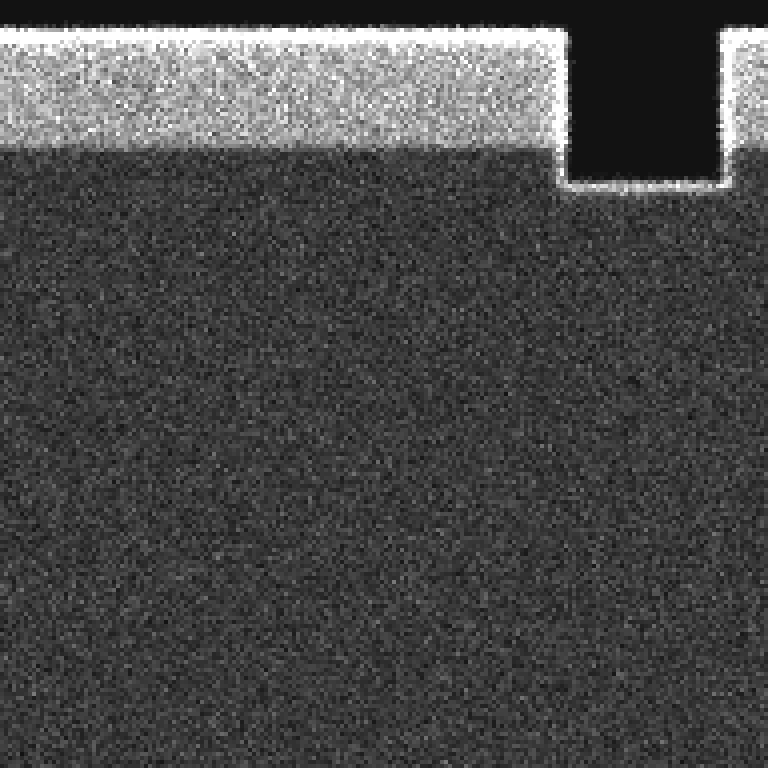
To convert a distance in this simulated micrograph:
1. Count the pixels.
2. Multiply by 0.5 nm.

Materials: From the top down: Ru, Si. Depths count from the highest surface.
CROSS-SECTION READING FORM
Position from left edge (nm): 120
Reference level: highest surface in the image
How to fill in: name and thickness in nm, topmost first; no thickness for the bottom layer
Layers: Ru 58, Si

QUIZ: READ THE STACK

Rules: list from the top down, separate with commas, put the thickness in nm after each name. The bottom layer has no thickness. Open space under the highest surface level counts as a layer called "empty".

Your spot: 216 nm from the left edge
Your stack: Ru 58, Si